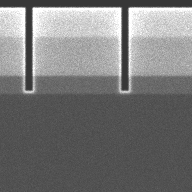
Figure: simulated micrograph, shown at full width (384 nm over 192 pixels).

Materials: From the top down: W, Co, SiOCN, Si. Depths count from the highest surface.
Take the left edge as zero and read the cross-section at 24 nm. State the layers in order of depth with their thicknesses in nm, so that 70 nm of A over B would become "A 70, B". W 58, Co 78, SiOCN 36, Si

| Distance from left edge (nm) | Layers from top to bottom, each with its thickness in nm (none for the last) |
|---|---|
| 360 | W 58, Co 78, SiOCN 36, Si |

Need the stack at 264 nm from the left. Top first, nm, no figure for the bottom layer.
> W 58, Co 78, SiOCN 36, Si